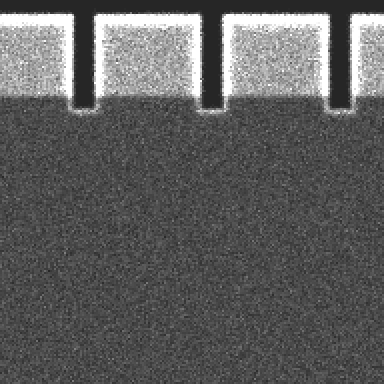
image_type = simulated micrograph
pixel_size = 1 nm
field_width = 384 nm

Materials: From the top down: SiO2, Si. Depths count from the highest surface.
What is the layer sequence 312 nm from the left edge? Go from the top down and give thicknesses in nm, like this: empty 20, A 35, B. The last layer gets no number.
SiO2 80, Si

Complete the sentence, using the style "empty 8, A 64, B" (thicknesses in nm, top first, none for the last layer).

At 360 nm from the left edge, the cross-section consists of SiO2 80, Si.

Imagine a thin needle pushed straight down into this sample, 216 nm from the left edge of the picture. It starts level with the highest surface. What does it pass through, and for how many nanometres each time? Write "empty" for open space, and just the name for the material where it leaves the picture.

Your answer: empty 94, Si